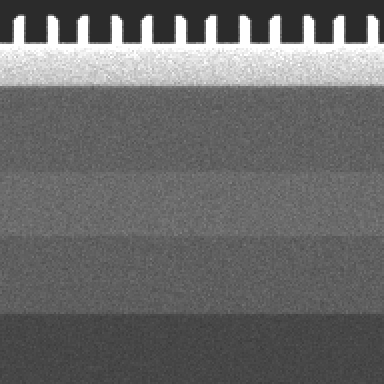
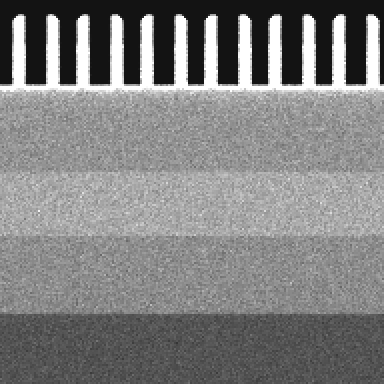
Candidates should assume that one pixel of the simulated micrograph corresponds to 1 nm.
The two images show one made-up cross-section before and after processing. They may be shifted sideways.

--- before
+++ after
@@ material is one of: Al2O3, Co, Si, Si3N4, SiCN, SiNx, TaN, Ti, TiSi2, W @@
W removed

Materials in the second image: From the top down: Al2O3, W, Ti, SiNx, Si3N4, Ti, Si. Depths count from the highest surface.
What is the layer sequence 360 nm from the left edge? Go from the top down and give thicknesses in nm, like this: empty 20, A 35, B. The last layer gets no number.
empty 70, Ti 24, SiNx 62, Si3N4 64, Ti 78, Si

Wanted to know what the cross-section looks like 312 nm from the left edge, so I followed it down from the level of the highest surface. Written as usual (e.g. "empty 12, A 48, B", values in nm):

empty 4, Al2O3 24, W 42, Ti 24, SiNx 62, Si3N4 64, Ti 78, Si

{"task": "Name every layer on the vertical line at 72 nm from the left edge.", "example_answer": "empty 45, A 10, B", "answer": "empty 70, Ti 24, SiNx 62, Si3N4 64, Ti 78, Si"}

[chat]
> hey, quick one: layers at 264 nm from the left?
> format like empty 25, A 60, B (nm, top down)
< empty 70, Ti 24, SiNx 62, Si3N4 64, Ti 78, Si